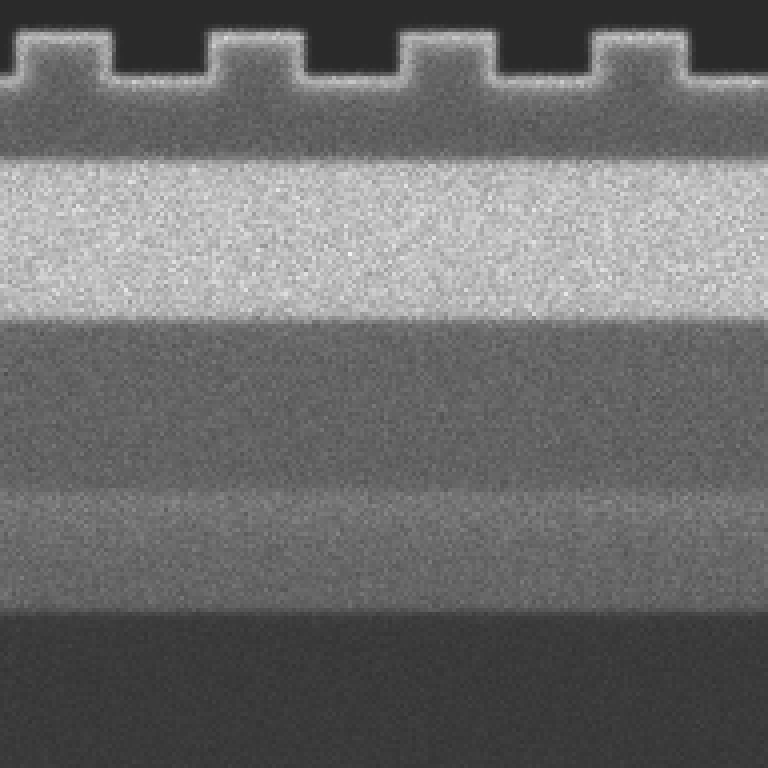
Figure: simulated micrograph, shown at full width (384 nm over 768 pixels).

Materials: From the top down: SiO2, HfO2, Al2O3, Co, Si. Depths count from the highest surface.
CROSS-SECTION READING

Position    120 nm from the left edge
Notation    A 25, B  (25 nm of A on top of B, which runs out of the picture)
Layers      SiO2 64, HfO2 80, Al2O3 86, Co 60, Si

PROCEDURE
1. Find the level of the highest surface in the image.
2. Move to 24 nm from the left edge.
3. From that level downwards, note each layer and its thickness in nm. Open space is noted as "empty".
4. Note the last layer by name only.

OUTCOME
SiO2 64, HfO2 80, Al2O3 86, Co 60, Si